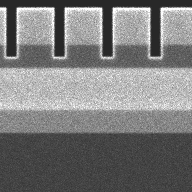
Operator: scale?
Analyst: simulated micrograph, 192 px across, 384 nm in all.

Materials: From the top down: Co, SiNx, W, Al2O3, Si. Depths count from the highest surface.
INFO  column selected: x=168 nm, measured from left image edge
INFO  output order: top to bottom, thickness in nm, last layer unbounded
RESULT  Co 74, SiNx 46, W 84, Al2O3 46, Si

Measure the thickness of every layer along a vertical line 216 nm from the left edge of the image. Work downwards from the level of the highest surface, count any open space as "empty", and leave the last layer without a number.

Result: empty 98, SiNx 22, W 84, Al2O3 46, Si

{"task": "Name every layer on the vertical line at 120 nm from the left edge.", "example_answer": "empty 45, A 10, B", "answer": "empty 98, SiNx 22, W 84, Al2O3 46, Si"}